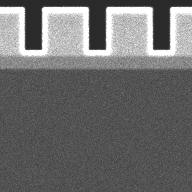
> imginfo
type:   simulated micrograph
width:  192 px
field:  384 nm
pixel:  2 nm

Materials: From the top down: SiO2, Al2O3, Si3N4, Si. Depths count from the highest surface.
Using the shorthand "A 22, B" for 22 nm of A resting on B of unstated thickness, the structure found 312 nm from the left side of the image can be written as empty 86, Al2O3 10, Si3N4 26, Si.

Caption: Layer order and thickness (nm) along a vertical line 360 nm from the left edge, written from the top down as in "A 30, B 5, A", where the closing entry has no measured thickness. SiO2 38, Al2O3 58, Si3N4 26, Si